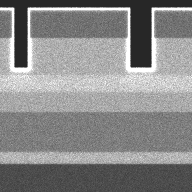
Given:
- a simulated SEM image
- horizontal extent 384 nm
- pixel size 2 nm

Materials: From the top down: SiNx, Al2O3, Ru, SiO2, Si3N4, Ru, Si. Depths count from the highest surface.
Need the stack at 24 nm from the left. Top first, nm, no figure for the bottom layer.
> SiNx 60, Al2O3 74, Ru 34, SiO2 40, Si3N4 80, Ru 24, Si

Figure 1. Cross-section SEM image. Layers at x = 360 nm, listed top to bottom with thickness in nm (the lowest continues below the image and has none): SiNx 60, Al2O3 74, Ru 34, SiO2 40, Si3N4 80, Ru 24, Si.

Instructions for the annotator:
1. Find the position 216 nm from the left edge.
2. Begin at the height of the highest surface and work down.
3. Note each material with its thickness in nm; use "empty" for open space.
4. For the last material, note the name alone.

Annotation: SiNx 60, Al2O3 74, Ru 34, SiO2 40, Si3N4 80, Ru 24, Si